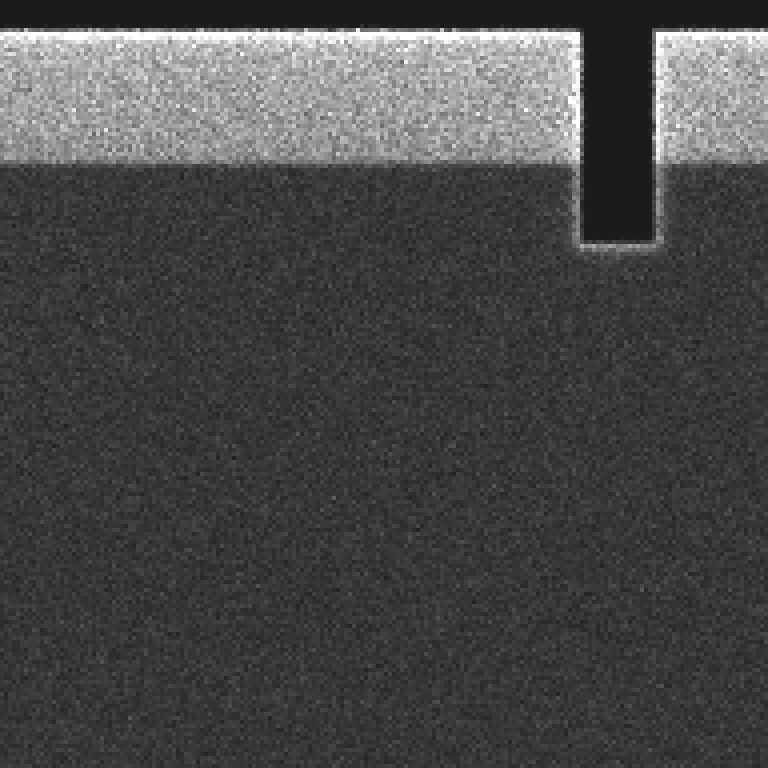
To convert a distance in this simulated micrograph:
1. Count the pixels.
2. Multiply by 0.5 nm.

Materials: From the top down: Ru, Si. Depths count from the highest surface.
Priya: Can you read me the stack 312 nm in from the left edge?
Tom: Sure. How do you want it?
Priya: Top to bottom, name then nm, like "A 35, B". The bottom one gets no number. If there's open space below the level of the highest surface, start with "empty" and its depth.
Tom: empty 106, Si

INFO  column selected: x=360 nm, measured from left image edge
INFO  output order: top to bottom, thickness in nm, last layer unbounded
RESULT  Ru 66, Si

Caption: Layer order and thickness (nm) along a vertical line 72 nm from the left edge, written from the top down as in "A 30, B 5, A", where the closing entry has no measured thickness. Ru 66, Si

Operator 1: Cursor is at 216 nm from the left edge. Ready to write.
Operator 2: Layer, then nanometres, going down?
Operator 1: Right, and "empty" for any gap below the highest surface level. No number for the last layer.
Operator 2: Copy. Ru 66, Si